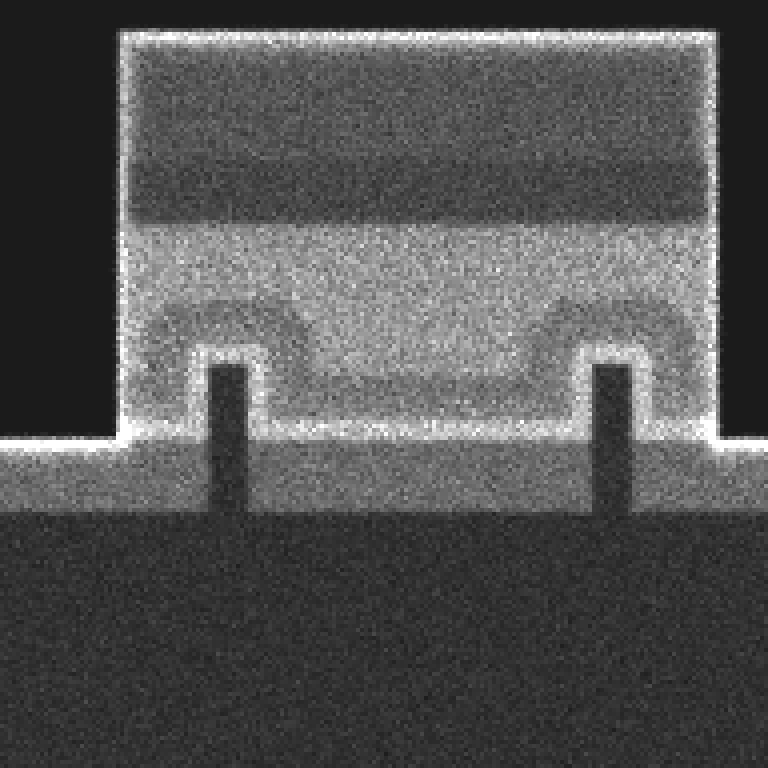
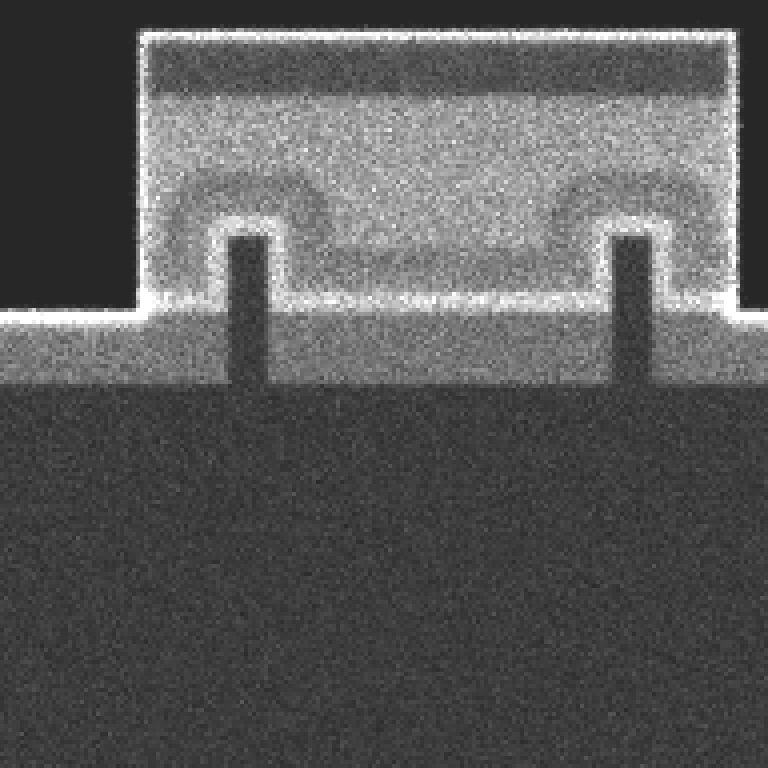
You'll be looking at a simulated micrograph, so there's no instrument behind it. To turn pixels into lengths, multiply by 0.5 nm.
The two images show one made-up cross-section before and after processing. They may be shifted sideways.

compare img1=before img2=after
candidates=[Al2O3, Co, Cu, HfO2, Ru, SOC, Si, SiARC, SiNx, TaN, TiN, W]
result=removed:SOC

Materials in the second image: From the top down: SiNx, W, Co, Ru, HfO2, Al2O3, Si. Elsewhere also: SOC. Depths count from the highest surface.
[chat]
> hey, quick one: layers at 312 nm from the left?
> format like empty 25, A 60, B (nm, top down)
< SiNx 32, W 38, Co 10, Ru 12, HfO2 10, Si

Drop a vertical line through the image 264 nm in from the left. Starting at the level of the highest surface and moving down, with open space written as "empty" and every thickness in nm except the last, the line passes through SiNx 32, W 76, Co 10, Ru 12, HfO2 10, Al2O3 36, Si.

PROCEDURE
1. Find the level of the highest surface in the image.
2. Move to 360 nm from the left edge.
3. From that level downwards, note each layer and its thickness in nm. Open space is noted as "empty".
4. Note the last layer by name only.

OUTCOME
SiNx 32, W 76, Co 10, Ru 12, HfO2 10, Al2O3 36, Si